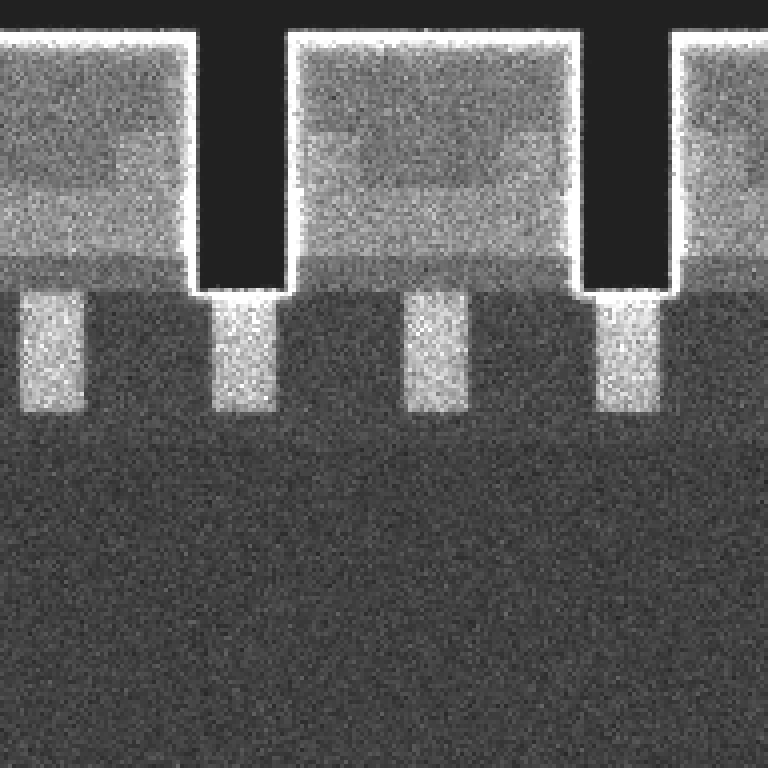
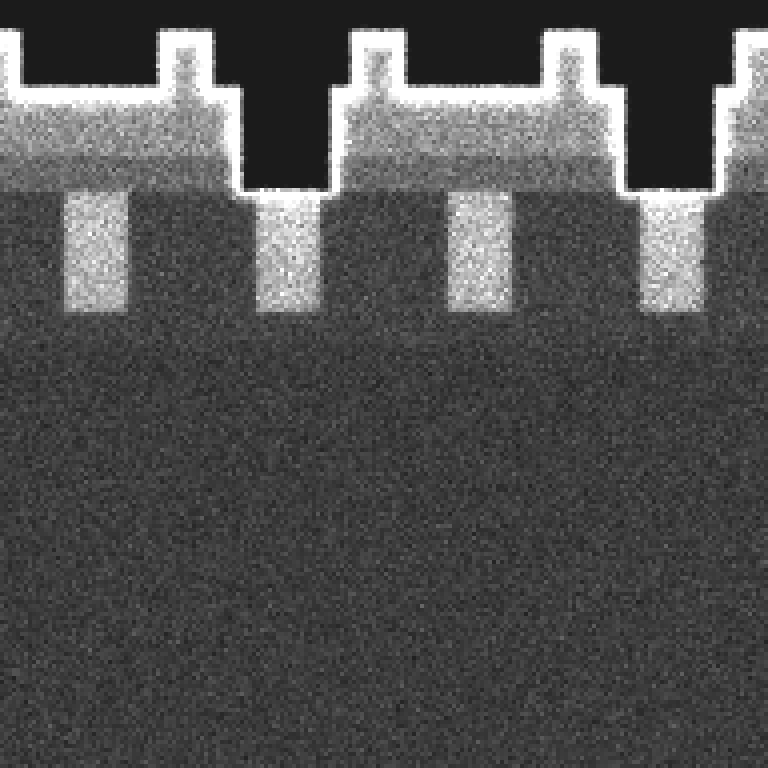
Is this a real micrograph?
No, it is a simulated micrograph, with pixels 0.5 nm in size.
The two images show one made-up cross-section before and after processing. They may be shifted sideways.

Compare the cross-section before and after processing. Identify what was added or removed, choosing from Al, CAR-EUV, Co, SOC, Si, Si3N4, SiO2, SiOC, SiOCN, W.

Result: SOC removed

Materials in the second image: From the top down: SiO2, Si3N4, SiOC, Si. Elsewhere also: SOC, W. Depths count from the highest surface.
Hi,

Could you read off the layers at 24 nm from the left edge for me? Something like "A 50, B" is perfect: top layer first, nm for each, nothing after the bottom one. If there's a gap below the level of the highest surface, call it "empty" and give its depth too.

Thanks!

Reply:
empty 28, SiO2 34, Si3N4 18, SiOC 76, Si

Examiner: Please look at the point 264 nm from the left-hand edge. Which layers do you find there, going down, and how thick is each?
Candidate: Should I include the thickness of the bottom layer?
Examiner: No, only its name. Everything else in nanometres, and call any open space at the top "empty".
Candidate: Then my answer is empty 28, SiO2 34, Si3N4 18, SiOC 76, Si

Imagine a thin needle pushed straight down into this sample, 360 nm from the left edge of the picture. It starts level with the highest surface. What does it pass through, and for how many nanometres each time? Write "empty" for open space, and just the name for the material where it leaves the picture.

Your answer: empty 28, SiO2 34, Si3N4 18, SiOC 76, Si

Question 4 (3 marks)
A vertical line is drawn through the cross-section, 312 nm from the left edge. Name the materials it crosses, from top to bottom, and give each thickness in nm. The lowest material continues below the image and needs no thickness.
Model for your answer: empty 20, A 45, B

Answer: empty 80, SiOC 76, Si